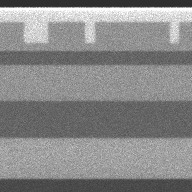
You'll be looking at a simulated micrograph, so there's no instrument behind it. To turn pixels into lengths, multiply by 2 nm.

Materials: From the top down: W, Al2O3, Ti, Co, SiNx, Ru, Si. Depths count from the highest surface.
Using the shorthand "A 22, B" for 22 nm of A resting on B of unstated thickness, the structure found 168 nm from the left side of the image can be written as W 28, Al2O3 58, Ti 28, Co 72, SiNx 74, Ru 82, Si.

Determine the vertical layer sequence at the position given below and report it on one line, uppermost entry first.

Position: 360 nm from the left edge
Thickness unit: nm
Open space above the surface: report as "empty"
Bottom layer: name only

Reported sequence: W 28, Al2O3 58, Ti 28, Co 72, SiNx 74, Ru 82, Si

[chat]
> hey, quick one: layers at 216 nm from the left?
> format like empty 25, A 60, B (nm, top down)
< W 28, Al2O3 58, Ti 28, Co 72, SiNx 74, Ru 82, Si